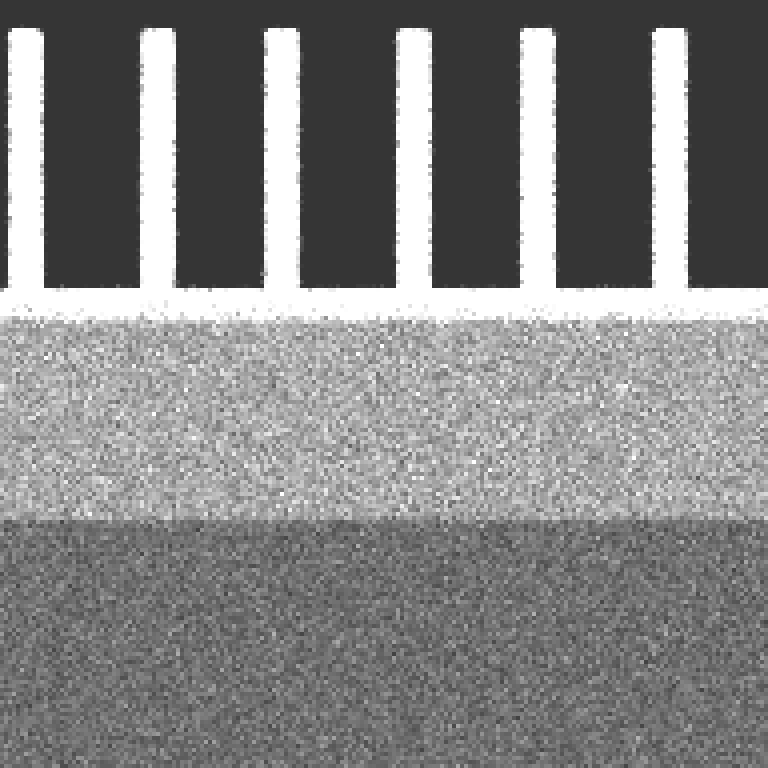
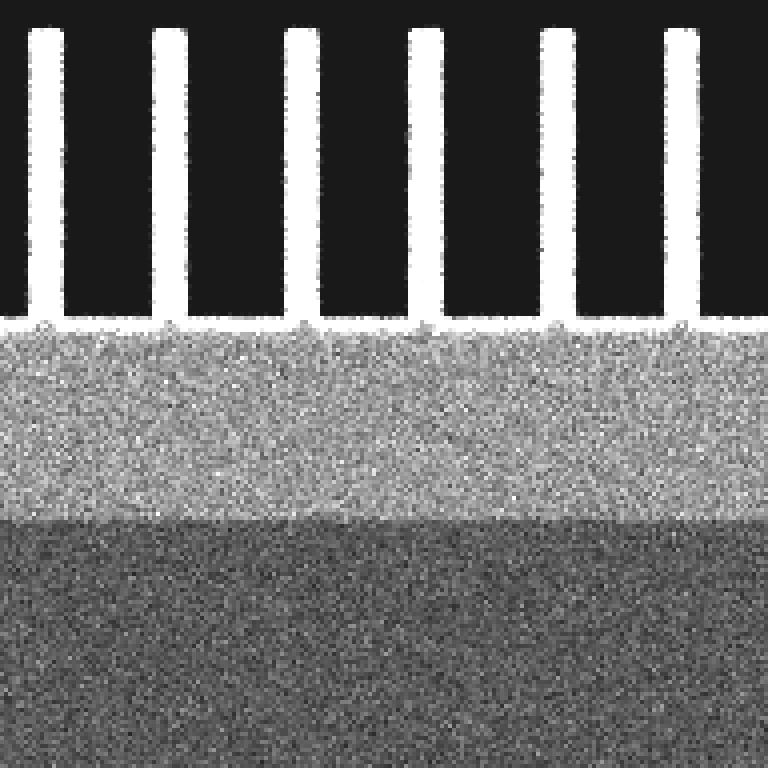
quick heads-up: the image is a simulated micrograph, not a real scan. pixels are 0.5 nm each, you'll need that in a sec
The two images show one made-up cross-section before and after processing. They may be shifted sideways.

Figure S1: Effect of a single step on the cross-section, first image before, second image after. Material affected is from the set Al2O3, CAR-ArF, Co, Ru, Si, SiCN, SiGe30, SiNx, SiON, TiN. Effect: removed Co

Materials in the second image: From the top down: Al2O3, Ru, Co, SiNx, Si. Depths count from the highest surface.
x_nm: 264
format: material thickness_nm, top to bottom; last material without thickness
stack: empty 144, SiNx 100, Si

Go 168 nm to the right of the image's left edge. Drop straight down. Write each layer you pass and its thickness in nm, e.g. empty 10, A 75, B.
empty 144, SiNx 100, Si